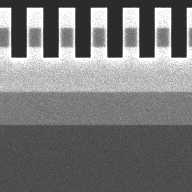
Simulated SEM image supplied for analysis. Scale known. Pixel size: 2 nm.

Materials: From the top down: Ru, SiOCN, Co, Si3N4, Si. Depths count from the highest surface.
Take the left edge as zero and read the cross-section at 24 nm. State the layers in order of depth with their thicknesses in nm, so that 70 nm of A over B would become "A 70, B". empty 100, Co 68, Si3N4 66, Si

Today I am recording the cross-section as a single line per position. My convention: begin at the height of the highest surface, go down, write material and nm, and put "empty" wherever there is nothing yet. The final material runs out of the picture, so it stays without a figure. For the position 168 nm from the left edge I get empty 100, Co 68, Si3N4 66, Si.